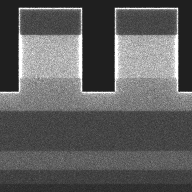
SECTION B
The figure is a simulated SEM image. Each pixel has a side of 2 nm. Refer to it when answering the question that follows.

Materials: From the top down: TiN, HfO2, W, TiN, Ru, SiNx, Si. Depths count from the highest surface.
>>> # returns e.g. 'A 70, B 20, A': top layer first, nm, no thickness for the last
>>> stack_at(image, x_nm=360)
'empty 168, W 38, TiN 80, Ru 38, SiNx 28, Si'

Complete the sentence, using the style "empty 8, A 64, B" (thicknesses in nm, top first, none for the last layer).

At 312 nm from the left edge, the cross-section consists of TiN 54, HfO2 86, W 66, TiN 80, Ru 38, SiNx 28, Si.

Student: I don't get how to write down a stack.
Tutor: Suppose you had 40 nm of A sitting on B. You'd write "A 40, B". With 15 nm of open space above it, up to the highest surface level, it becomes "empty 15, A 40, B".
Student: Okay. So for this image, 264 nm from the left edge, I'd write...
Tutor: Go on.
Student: TiN 54, HfO2 86, W 66, TiN 80, Ru 38, SiNx 28, Si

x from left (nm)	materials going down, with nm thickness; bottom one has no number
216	empty 168, W 38, TiN 80, Ru 38, SiNx 28, Si